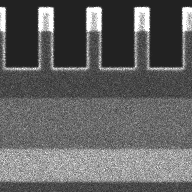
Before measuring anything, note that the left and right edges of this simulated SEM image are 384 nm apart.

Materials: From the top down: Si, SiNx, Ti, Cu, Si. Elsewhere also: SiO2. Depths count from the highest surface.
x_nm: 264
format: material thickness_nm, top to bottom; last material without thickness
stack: empty 120, Si 60, SiNx 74, Ti 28, Cu 66, Si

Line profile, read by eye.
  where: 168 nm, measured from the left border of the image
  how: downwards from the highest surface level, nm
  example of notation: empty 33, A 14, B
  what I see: empty 120, Si 60, SiNx 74, Ti 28, Cu 66, Si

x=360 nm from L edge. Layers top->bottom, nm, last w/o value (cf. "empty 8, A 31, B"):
empty 120, Si 60, SiNx 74, Ti 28, Cu 66, Si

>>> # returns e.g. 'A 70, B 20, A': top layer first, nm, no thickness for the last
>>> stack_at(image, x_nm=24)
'empty 120, Si 60, SiNx 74, Ti 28, Cu 66, Si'